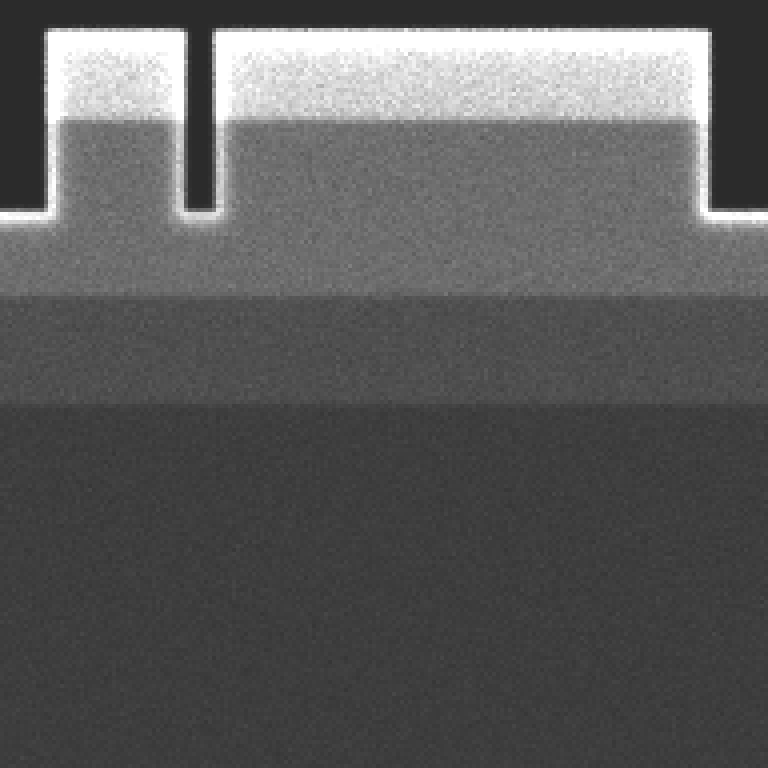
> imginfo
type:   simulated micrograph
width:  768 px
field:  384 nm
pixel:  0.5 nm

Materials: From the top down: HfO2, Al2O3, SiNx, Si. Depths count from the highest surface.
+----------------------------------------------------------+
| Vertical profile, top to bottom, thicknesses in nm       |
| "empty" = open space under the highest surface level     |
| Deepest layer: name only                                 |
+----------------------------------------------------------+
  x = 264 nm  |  HfO2 44, Al2O3 88, SiNx 54, Si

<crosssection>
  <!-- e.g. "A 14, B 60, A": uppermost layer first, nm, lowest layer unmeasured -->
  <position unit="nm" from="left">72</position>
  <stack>HfO2 44, Al2O3 88, SiNx 54, Si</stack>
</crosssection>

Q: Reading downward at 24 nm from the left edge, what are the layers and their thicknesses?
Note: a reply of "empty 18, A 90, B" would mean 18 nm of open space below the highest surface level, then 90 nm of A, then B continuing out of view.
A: HfO2 44, Al2O3 88, SiNx 54, Si